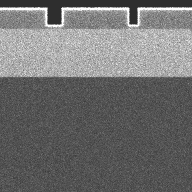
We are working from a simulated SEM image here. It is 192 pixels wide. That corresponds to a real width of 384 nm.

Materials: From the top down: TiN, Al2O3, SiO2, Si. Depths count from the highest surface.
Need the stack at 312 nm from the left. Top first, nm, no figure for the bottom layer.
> TiN 42, Al2O3 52, SiO2 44, Si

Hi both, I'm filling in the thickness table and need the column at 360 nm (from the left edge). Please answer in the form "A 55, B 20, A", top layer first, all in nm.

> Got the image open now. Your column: TiN 42, Al2O3 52, SiO2 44, Si